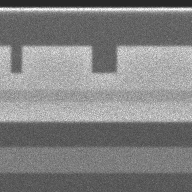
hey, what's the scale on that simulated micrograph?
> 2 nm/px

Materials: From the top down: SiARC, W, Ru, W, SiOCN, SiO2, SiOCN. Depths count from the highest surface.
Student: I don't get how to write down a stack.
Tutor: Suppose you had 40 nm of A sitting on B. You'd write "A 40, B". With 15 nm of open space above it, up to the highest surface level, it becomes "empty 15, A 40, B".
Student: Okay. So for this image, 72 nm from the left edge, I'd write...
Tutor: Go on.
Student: SiARC 76, W 88, Ru 24, W 40, SiOCN 50, SiO2 52, SiOCN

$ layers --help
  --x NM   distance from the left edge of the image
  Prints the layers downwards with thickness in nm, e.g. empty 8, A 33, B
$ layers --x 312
SiARC 76, W 88, Ru 24, W 40, SiOCN 50, SiO2 52, SiOCN